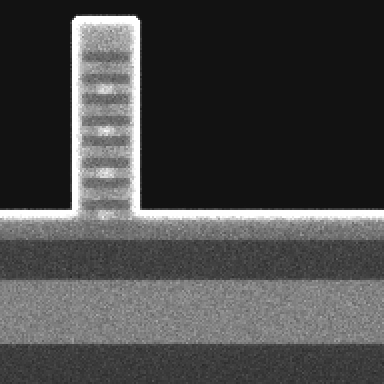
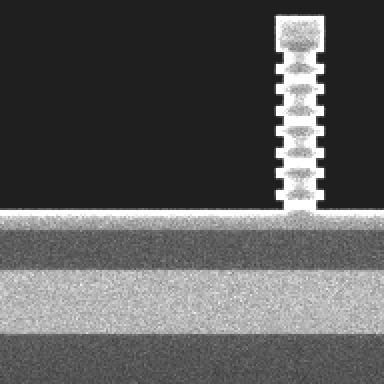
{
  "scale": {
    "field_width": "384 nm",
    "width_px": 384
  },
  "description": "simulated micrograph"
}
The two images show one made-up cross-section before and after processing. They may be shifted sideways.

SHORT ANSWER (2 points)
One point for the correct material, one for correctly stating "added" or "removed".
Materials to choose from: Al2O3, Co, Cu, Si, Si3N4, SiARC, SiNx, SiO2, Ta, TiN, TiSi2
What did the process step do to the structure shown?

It removed Al2O3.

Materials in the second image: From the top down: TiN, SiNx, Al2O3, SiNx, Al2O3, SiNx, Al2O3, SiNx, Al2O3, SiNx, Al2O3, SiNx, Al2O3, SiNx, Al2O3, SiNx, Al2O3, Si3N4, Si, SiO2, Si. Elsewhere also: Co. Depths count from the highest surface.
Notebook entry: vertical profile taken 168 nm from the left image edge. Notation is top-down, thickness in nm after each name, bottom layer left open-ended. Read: empty 194, Si3N4 20, Si 40, SiO2 64, Si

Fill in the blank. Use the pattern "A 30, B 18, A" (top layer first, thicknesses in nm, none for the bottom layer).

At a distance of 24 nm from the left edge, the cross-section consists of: empty 194, Si3N4 20, Si 40, SiO2 64, Si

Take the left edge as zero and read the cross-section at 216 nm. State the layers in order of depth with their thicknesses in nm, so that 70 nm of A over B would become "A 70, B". empty 194, Si3N4 20, Si 40, SiO2 64, Si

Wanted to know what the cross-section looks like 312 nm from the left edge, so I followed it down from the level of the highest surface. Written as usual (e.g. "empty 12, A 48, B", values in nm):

TiN 26, SiNx 10, Al2O3 12, SiNx 10, Al2O3 10, SiNx 10, Al2O3 12, SiNx 10, Al2O3 10, SiNx 10, Al2O3 12, SiNx 10, Al2O3 10, SiNx 10, Al2O3 12, SiNx 10, Al2O3 10, Si3N4 20, Si 40, SiO2 64, Si